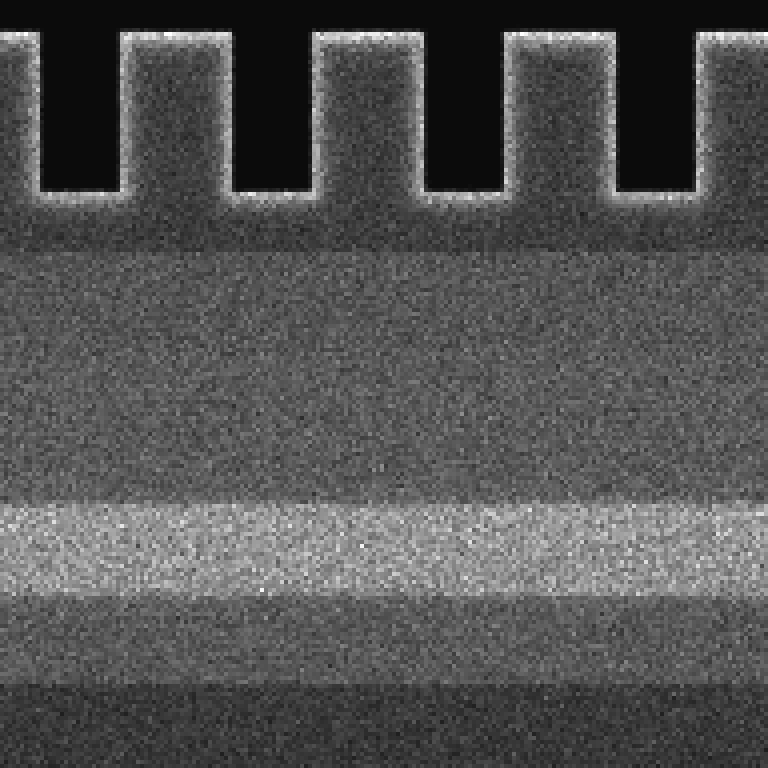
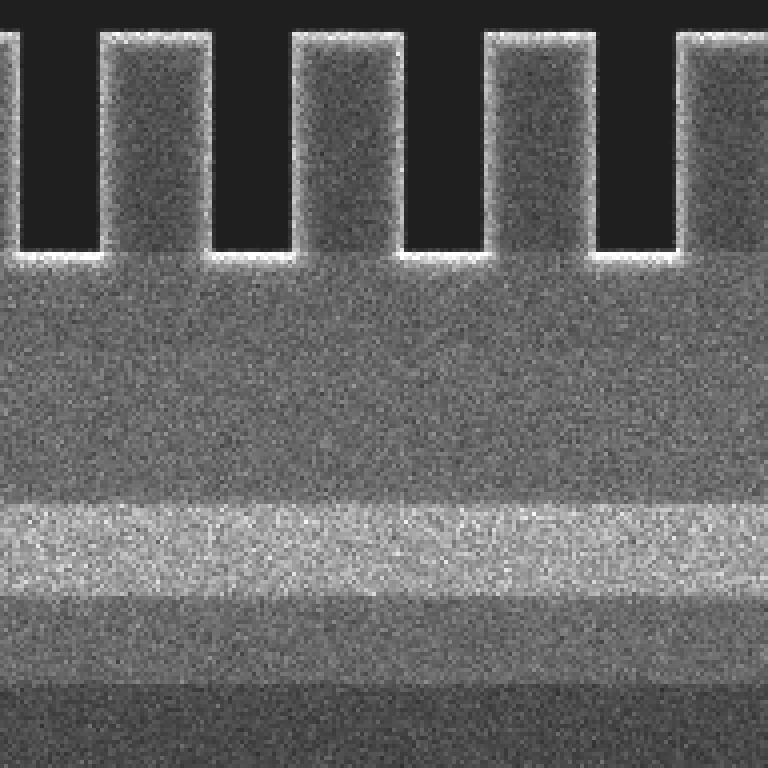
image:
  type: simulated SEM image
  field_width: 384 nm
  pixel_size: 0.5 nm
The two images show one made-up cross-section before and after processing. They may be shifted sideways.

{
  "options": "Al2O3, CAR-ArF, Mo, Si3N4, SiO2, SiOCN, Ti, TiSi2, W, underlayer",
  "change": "removed",
  "material": "underlayer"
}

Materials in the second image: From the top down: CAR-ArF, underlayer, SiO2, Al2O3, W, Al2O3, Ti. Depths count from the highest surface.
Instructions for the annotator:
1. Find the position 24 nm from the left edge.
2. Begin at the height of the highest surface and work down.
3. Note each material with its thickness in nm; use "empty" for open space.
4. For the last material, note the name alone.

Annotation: empty 110, SiO2 50, Al2O3 76, W 46, Al2O3 44, Ti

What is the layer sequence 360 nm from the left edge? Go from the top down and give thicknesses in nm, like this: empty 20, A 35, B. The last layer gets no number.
CAR-ArF 80, underlayer 30, SiO2 50, Al2O3 76, W 46, Al2O3 44, Ti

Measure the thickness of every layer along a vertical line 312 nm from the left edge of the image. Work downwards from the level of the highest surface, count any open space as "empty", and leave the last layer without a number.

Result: empty 110, SiO2 50, Al2O3 76, W 46, Al2O3 44, Ti